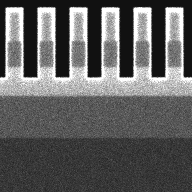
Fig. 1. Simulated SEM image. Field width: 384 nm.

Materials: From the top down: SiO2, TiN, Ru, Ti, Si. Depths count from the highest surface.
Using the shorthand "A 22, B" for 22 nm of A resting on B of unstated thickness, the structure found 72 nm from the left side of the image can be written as empty 140, Ru 36, Ti 84, Si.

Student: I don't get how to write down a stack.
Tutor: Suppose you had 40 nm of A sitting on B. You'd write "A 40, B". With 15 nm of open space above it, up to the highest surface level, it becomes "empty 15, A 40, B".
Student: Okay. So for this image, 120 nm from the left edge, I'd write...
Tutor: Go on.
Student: empty 140, Ru 36, Ti 84, Si